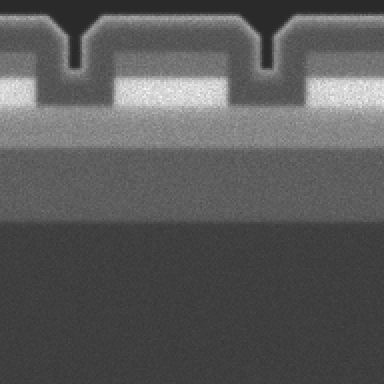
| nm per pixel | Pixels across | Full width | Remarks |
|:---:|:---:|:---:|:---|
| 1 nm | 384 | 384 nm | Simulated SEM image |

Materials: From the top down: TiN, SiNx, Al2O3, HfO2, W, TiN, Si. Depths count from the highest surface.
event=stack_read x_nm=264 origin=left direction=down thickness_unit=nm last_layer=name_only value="empty 54, TiN 12, SiNx 24, W 42, TiN 74, Si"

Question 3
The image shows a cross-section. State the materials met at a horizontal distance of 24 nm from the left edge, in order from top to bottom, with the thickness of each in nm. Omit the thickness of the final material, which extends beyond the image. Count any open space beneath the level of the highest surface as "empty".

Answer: TiN 12, SiNx 24, Al2O3 26, HfO2 28, W 42, TiN 74, Si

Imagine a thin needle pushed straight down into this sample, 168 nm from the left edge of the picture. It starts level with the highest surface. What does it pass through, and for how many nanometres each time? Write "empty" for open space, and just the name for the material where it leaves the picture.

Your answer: TiN 12, SiNx 24, Al2O3 26, HfO2 28, W 42, TiN 74, Si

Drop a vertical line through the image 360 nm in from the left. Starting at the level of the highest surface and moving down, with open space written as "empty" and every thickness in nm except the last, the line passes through TiN 12, SiNx 24, Al2O3 26, HfO2 28, W 42, TiN 74, Si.